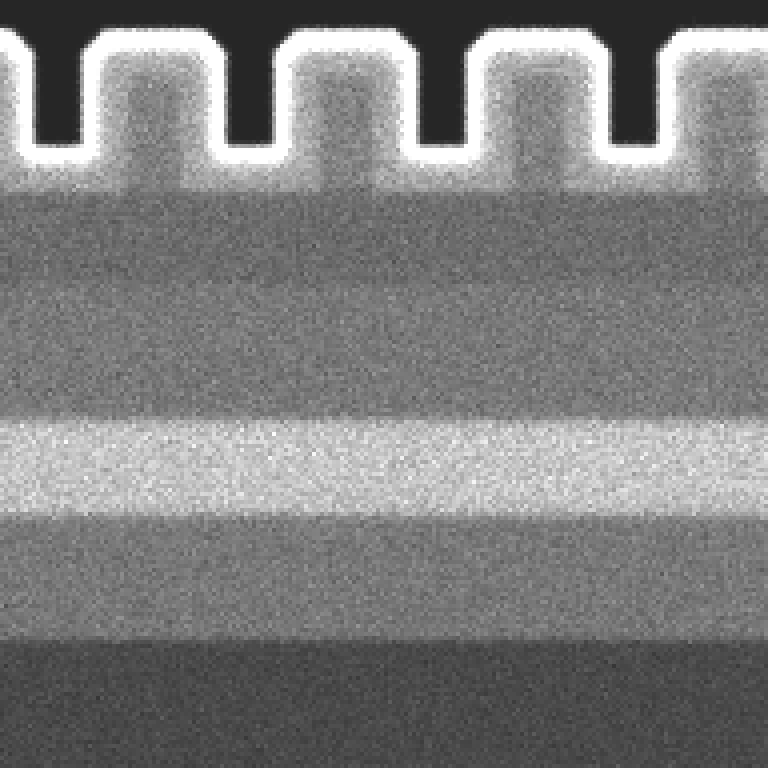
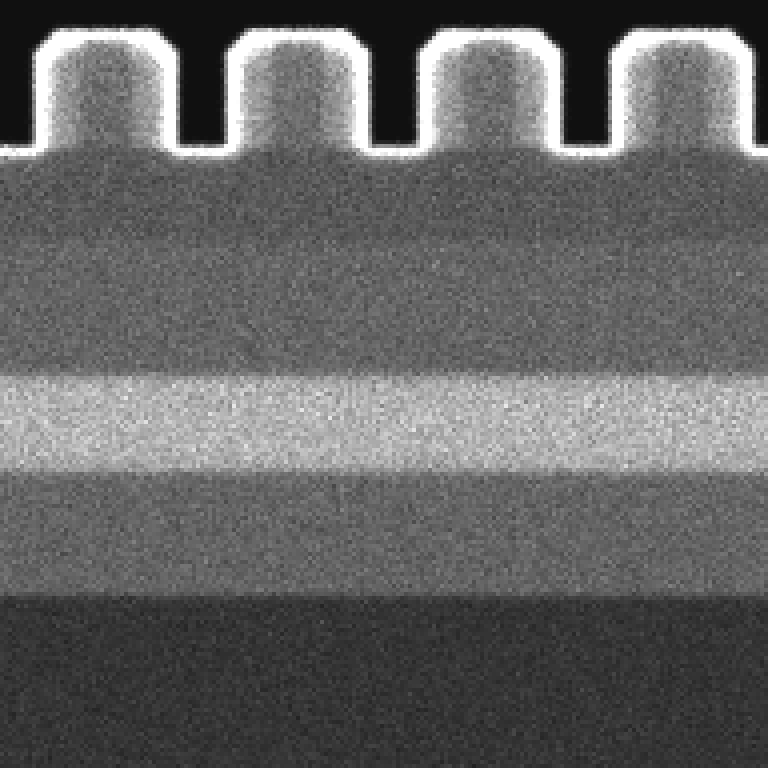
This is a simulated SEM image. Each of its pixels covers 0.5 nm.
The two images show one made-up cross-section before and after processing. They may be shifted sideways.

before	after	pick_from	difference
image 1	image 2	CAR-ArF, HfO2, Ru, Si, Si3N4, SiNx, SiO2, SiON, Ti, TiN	SiO2 removed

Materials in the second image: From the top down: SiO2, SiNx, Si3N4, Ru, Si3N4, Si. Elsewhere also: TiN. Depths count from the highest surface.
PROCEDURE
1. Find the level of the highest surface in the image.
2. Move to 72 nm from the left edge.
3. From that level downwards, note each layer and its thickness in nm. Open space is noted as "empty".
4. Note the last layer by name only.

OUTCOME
SiO2 58, SiNx 46, Si3N4 68, Ru 48, Si3N4 62, Si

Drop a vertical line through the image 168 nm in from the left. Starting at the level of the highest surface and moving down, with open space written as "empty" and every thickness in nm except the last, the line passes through SiO2 58, SiNx 46, Si3N4 68, Ru 48, Si3N4 62, Si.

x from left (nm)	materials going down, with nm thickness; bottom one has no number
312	empty 4, SiO2 54, SiNx 46, Si3N4 68, Ru 48, Si3N4 62, Si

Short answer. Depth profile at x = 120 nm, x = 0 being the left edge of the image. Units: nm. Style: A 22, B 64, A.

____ empty 4, SiO2 54, SiNx 46, Si3N4 68, Ru 48, Si3N4 62, Si